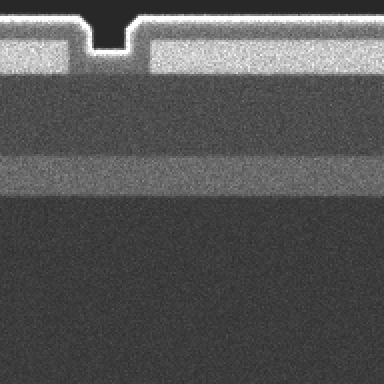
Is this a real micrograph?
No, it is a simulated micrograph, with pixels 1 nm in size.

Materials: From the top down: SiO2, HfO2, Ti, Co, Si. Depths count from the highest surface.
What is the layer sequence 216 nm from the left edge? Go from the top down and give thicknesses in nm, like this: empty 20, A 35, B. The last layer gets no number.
SiO2 24, HfO2 34, Ti 82, Co 40, Si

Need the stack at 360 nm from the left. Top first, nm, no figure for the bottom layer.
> SiO2 24, HfO2 34, Ti 82, Co 40, Si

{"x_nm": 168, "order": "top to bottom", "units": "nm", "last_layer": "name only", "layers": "SiO2 24, HfO2 34, Ti 82, Co 40, Si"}